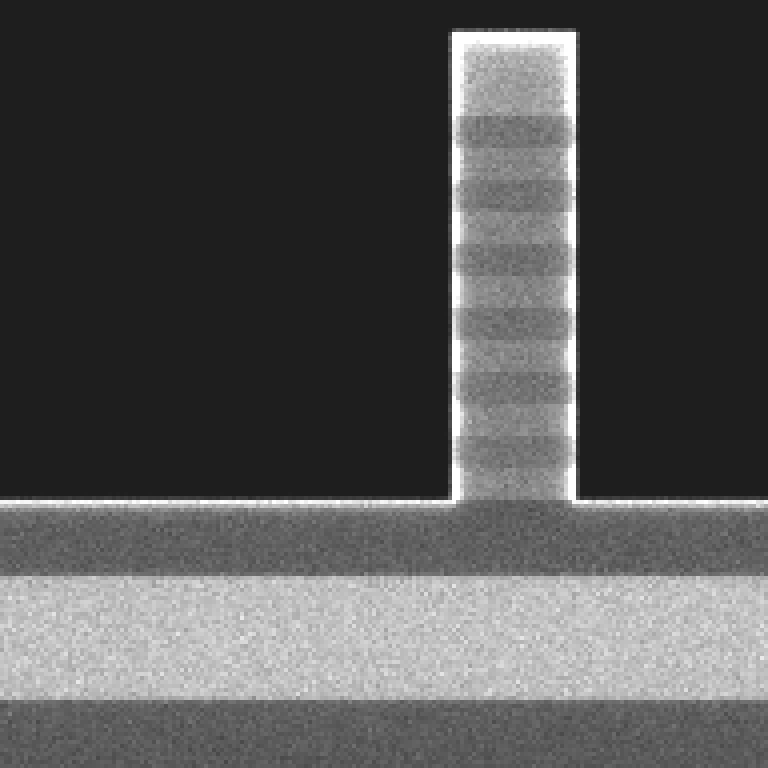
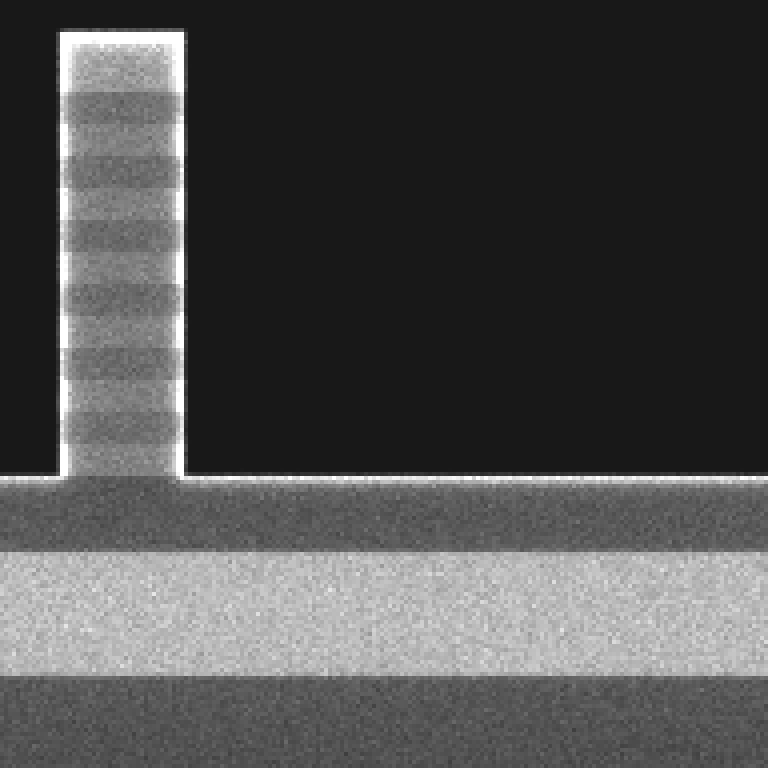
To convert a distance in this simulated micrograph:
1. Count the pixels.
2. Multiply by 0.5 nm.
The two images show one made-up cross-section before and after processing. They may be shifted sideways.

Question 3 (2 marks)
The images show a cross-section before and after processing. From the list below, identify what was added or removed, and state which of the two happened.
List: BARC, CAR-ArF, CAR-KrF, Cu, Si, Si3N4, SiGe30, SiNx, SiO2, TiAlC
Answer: Si3N4 was removed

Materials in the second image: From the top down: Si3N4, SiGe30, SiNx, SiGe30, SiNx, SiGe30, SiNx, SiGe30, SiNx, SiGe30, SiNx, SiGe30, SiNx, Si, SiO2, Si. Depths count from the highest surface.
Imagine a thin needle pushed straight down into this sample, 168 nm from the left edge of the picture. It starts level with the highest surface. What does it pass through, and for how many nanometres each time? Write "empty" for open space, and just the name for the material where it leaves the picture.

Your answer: empty 222, Si 38, SiO2 62, Si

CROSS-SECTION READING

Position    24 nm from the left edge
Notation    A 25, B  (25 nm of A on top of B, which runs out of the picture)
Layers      empty 222, Si 38, SiO2 62, Si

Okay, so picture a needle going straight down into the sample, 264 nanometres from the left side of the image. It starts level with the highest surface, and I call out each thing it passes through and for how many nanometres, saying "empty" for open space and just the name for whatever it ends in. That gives empty 222, Si 38, SiO2 62, Si